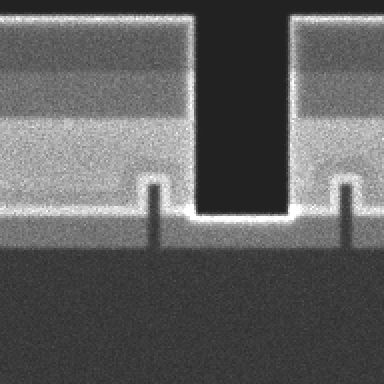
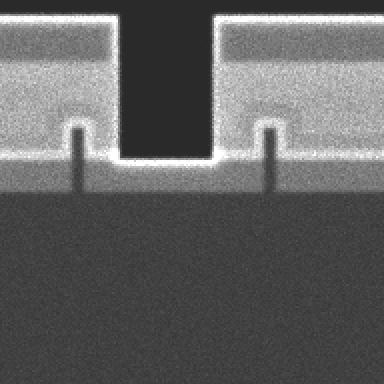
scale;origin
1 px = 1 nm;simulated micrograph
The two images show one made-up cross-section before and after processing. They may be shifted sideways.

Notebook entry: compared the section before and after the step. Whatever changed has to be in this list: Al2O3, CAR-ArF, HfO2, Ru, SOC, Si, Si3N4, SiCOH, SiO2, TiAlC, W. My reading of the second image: SOC removed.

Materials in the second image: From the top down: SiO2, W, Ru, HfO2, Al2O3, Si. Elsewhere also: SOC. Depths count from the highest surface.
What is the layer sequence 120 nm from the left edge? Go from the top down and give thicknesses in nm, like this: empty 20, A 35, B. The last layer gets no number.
empty 144, Al2O3 32, Si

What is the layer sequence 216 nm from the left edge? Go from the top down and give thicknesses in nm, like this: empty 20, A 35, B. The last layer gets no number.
SiO2 46, W 72, Ru 16, HfO2 10, Al2O3 32, Si